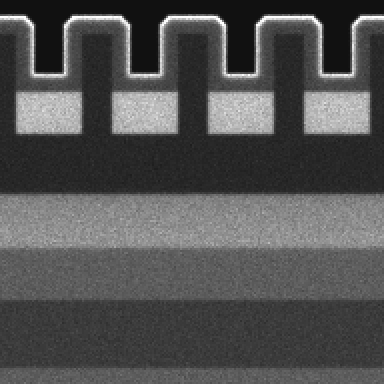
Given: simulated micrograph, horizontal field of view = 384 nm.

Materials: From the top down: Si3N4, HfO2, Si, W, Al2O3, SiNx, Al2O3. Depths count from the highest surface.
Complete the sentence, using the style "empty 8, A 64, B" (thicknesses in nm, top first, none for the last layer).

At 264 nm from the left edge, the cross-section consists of Si3N4 76, HfO2 42, Si 60, W 54, Al2O3 52, SiNx 68, Al2O3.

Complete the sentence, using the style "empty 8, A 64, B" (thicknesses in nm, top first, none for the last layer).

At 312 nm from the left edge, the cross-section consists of Si3N4 76, HfO2 42, Si 60, W 54, Al2O3 52, SiNx 68, Al2O3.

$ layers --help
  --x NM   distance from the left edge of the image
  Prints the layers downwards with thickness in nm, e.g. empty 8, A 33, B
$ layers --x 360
Si3N4 76, HfO2 42, Si 60, W 54, Al2O3 52, SiNx 68, Al2O3